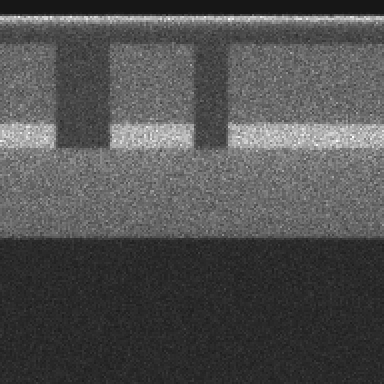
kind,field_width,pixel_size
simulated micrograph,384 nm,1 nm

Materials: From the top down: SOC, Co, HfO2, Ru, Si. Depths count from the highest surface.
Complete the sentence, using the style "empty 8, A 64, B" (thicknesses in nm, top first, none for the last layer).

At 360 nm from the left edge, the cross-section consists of SOC 28, Co 80, HfO2 24, Ru 90, Si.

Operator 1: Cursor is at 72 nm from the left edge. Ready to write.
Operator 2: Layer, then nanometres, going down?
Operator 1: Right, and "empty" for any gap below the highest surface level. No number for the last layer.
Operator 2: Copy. SOC 132, Ru 90, Si